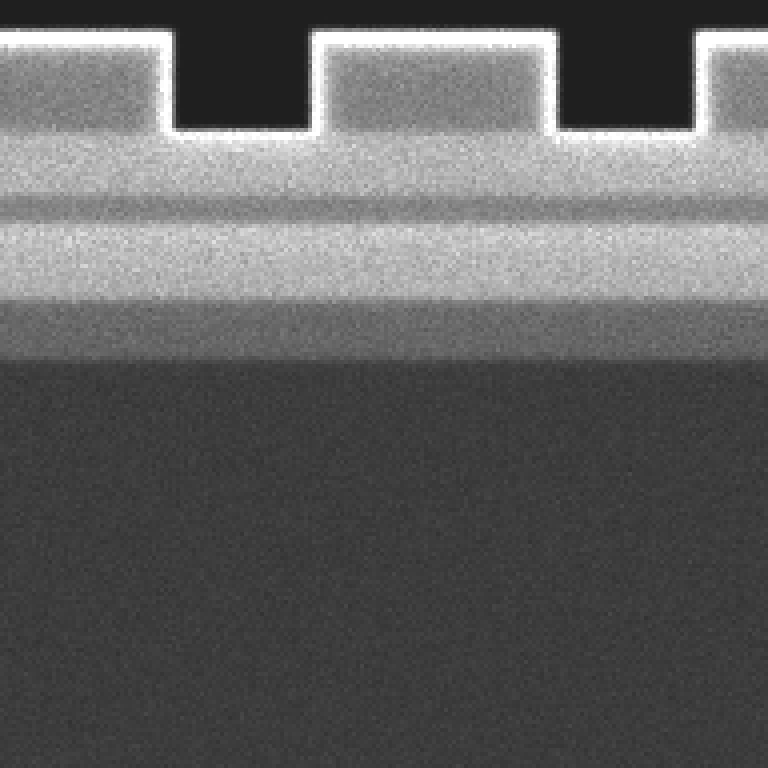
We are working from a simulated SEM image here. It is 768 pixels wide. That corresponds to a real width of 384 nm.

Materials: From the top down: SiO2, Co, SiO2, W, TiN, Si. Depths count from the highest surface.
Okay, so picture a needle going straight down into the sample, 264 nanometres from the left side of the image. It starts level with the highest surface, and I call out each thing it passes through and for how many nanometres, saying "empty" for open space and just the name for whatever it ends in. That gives SiO2 50, Co 32, SiO2 14, W 38, TiN 30, Si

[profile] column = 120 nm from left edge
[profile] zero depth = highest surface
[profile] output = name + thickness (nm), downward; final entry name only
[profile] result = empty 50, Co 32, SiO2 14, W 38, TiN 30, Si